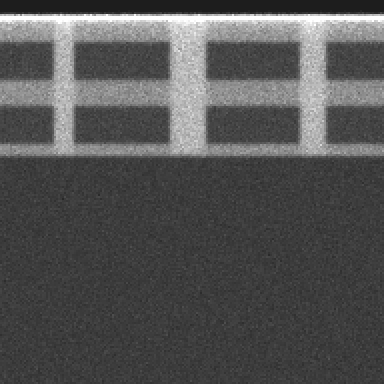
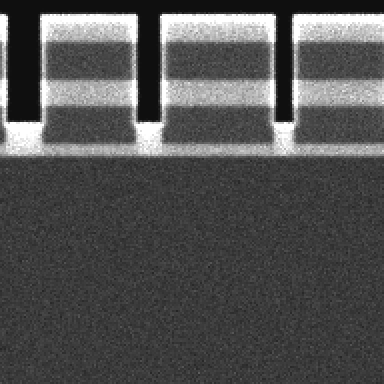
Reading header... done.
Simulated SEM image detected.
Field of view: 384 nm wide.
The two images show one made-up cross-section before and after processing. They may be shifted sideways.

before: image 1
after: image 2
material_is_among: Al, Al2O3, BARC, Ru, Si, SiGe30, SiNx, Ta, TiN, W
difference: W, removed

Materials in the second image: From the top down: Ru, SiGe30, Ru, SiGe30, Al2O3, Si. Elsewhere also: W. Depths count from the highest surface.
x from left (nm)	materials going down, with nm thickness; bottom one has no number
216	Ru 26, SiGe30 38, Ru 26, SiGe30 38, Al2O3 12, Si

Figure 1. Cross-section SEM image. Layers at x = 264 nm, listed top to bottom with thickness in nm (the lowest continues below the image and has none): Ru 26, SiGe30 38, Ru 26, SiGe30 38, Al2O3 12, Si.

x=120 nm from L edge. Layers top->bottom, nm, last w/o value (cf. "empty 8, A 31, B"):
Ru 26, SiGe30 38, Ru 26, SiGe30 38, Al2O3 12, Si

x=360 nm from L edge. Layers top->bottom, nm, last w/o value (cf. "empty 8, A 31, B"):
Ru 26, SiGe30 38, Ru 26, SiGe30 38, Al2O3 12, Si